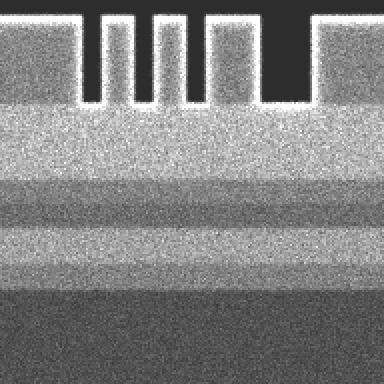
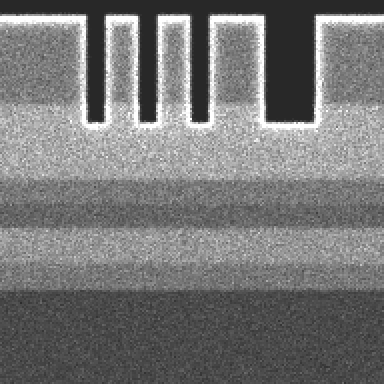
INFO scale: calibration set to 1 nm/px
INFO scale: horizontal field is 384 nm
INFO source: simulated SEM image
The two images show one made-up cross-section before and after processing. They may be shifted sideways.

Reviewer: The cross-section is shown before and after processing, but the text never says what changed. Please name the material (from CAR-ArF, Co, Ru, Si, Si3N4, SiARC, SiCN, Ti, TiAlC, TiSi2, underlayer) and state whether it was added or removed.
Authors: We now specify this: Ru, removed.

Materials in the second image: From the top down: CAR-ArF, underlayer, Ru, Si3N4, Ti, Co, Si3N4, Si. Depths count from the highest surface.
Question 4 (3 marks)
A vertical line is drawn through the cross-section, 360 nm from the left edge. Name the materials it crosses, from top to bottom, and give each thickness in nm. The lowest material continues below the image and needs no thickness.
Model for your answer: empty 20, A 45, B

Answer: CAR-ArF 34, underlayer 54, Ru 76, Si3N4 24, Ti 24, Co 36, Si3N4 26, Si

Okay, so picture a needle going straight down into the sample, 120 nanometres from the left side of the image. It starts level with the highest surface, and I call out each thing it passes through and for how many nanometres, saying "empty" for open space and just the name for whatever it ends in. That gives CAR-ArF 34, underlayer 54, Ru 76, Si3N4 24, Ti 24, Co 36, Si3N4 26, Si